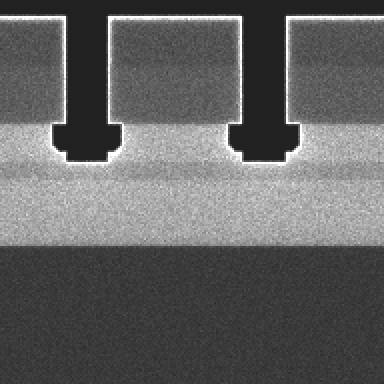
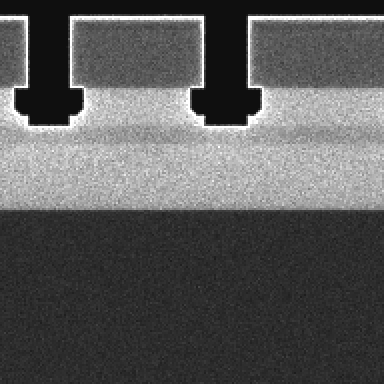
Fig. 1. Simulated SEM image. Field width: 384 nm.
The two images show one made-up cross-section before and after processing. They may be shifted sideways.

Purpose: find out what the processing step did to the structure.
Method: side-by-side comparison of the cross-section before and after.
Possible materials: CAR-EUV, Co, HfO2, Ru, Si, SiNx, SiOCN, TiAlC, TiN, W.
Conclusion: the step removed SiNx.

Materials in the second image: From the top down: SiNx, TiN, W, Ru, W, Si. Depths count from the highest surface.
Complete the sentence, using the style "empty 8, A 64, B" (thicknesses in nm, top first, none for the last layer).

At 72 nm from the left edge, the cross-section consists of SiNx 14, TiN 58, empty 28, W 10, Ru 18, W 66, Si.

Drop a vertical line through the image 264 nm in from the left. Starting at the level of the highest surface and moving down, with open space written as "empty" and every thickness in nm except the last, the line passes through SiNx 14, TiN 58, W 38, Ru 18, W 66, Si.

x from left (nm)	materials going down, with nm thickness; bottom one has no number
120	SiNx 14, TiN 58, W 38, Ru 18, W 66, Si